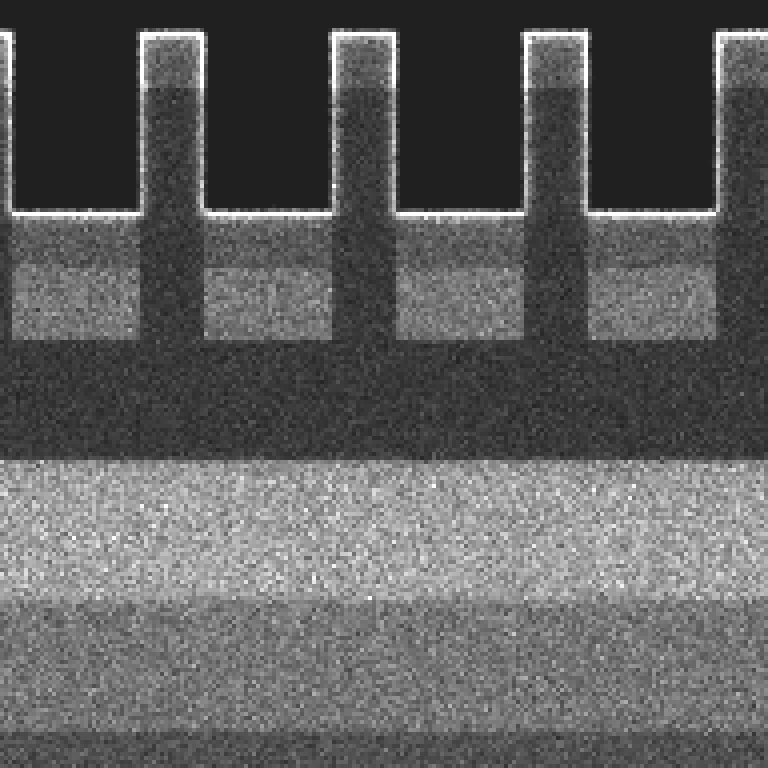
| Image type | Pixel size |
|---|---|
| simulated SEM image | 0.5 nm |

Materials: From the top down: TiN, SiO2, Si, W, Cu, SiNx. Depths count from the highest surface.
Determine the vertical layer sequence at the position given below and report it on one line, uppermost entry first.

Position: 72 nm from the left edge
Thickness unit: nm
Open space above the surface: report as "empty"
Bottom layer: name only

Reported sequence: TiN 28, Si 186, W 70, Cu 66, SiNx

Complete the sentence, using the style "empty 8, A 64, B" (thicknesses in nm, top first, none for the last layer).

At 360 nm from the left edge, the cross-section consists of TiN 28, Si 186, W 70, Cu 66, SiNx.